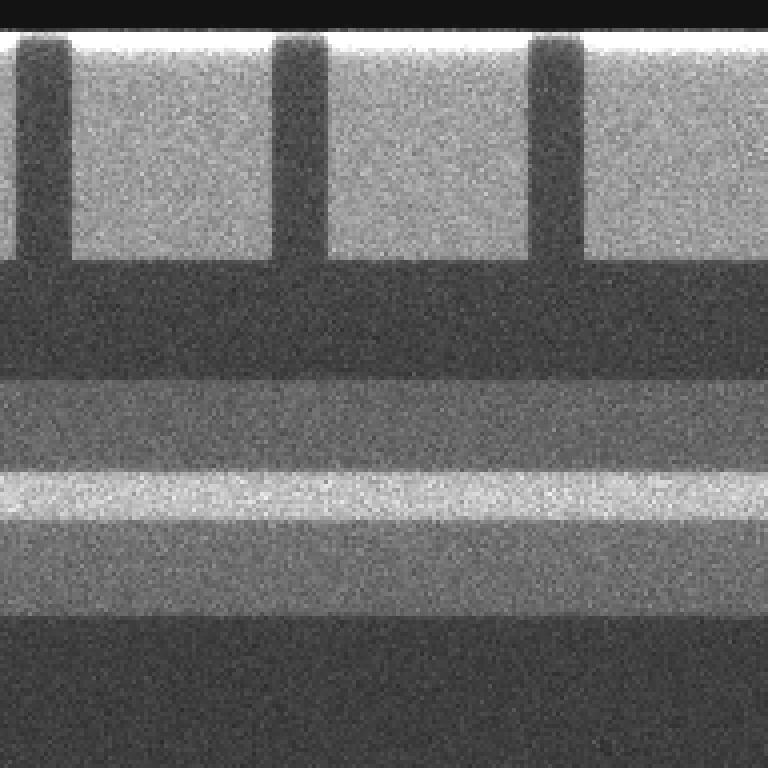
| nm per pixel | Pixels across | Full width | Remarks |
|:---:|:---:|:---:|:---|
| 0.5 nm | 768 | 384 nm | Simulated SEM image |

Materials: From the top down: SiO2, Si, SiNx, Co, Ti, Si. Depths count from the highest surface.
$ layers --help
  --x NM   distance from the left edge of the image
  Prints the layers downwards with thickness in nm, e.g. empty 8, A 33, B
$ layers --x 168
SiO2 114, Si 60, SiNx 46, Co 24, Ti 48, Si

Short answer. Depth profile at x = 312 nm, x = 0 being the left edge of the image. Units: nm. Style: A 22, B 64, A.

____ SiO2 114, Si 60, SiNx 46, Co 24, Ti 48, Si